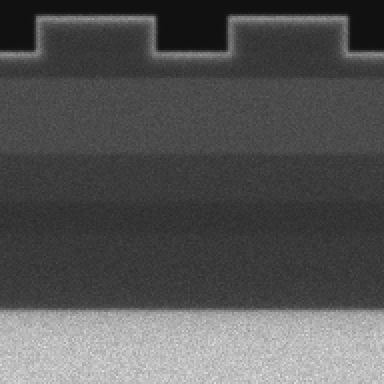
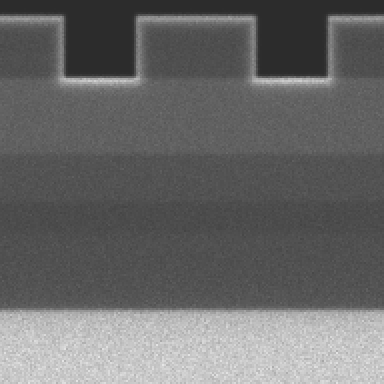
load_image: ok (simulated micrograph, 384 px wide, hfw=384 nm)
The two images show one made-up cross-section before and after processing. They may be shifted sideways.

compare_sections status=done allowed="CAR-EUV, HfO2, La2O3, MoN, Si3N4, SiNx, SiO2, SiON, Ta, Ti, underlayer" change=removed material="underlayer"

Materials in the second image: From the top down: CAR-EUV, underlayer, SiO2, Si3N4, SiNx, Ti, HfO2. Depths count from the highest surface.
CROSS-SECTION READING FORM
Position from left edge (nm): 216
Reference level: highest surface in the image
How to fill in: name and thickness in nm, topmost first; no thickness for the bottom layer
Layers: CAR-EUV 36, underlayer 26, SiO2 76, Si3N4 48, SiNx 32, Ti 76, HfO2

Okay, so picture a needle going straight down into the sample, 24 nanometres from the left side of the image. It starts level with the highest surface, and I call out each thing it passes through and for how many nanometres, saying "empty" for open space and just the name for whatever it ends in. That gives CAR-EUV 36, underlayer 26, SiO2 76, Si3N4 48, SiNx 32, Ti 76, HfO2